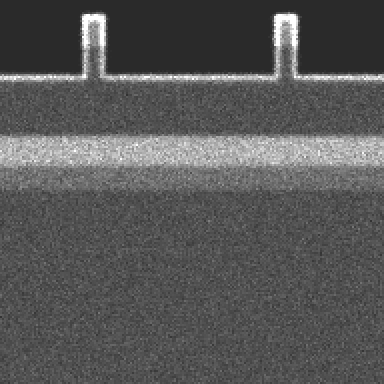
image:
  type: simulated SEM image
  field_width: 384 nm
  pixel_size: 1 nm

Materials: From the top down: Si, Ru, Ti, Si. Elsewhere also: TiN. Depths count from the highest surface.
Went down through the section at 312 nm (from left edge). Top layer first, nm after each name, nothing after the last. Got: empty 60, Si 60, Ru 30, Ti 24, Si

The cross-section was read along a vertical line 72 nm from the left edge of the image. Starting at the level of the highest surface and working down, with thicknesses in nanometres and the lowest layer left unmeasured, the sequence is empty 60, Si 60, Ru 30, Ti 24, Si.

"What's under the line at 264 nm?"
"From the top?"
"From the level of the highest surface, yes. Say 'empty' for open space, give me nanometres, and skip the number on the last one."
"empty 60, Si 60, Ru 30, Ti 24, Si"